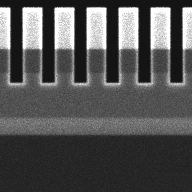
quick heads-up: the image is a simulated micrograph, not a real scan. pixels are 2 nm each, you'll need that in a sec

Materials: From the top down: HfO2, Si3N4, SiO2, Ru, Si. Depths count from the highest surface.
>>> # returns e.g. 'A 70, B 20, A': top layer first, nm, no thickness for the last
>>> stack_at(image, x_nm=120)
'HfO2 82, Si3N4 48, SiO2 90, Ru 34, Si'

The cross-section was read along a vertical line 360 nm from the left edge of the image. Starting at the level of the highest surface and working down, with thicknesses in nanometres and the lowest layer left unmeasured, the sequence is empty 150, SiO2 70, Ru 34, Si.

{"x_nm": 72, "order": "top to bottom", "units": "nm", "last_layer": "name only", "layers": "HfO2 82, Si3N4 48, SiO2 90, Ru 34, Si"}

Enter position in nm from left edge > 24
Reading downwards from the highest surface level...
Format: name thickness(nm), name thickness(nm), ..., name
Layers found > empty 150, SiO2 70, Ru 34, Si